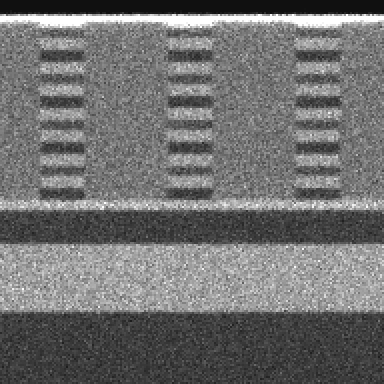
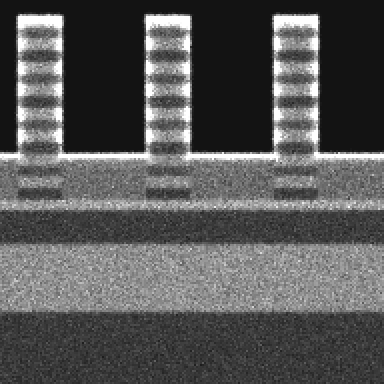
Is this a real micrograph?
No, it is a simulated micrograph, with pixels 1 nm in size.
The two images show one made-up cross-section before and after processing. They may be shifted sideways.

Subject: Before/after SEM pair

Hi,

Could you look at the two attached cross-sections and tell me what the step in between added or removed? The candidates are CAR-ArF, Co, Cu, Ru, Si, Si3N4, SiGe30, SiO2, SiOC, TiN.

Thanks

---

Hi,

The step removed Si3N4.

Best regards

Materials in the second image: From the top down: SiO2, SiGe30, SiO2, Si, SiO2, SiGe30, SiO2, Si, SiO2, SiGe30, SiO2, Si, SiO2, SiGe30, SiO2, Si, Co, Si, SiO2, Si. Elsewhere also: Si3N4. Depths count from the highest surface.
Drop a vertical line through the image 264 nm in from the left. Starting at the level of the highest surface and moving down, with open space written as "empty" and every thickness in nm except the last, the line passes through empty 138, Si3N4 46, Co 10, Si 34, SiO2 68, Si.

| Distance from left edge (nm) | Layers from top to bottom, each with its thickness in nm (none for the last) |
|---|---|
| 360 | empty 138, Si3N4 46, Co 10, Si 34, SiO2 68, Si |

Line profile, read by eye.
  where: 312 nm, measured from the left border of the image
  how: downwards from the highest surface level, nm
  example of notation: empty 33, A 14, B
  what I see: SiO2 12, SiGe30 10, SiO2 12, Si 12, SiO2 12, SiGe30 10, SiO2 12, Si 12, SiO2 12, SiGe30 10, SiO2 12, Si 12, SiO2 12, SiGe30 10, SiO2 12, Si 12, Co 10, Si 34, SiO2 68, Si